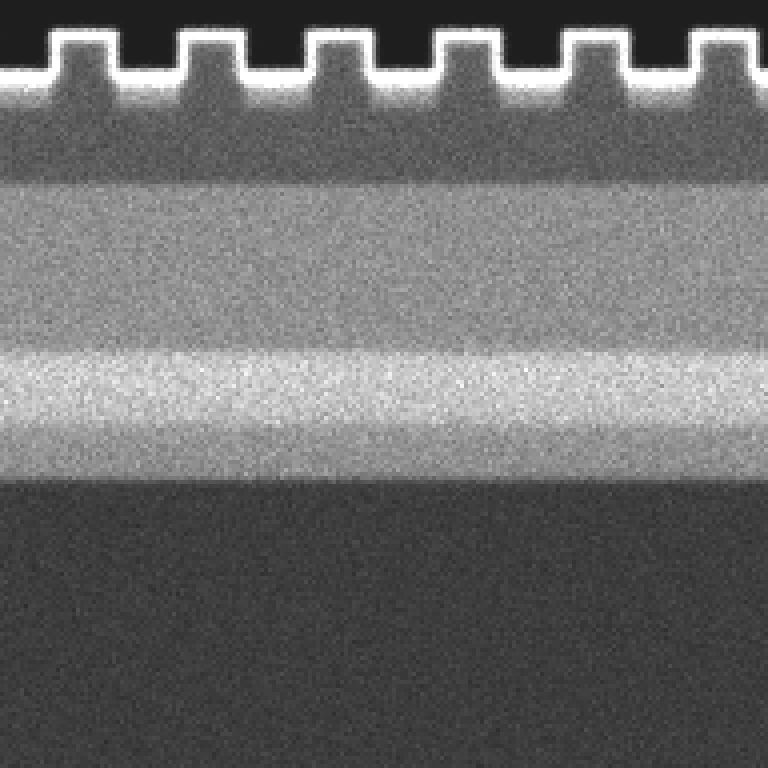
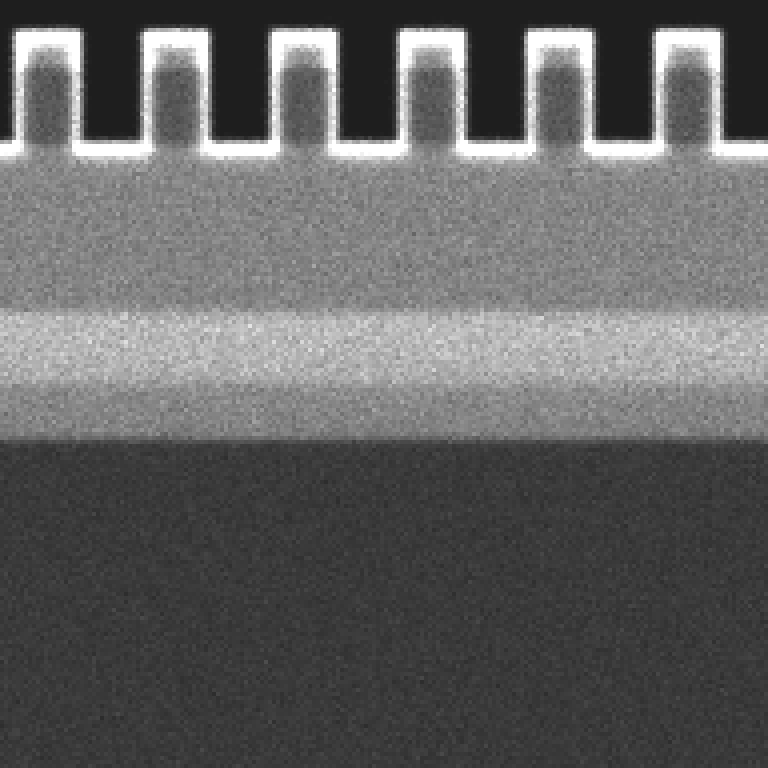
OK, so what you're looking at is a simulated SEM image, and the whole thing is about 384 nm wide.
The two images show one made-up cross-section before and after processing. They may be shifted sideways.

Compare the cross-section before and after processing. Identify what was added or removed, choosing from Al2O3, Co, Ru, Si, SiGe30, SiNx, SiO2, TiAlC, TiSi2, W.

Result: SiNx removed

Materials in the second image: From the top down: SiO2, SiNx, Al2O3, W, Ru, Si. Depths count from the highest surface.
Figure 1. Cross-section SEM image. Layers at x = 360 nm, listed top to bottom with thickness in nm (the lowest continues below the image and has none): empty 56, Al2O3 84, W 36, Ru 28, Si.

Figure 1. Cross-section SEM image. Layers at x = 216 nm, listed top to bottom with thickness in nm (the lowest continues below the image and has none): SiO2 18, SiNx 38, Al2O3 84, W 36, Ru 28, Si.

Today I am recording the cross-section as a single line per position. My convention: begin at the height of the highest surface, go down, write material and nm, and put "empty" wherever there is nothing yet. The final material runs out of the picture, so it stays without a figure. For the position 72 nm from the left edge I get SiO2 18, SiNx 38, Al2O3 84, W 36, Ru 28, Si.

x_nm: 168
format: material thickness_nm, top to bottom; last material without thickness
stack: empty 56, Al2O3 84, W 36, Ru 28, Si